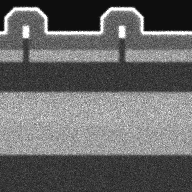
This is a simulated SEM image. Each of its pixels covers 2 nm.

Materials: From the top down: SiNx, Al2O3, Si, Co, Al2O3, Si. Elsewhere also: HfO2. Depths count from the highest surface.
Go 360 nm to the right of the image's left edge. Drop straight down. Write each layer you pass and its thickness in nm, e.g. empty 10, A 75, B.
empty 48, SiNx 36, Al2O3 24, Si 60, Co 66, Al2O3 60, Si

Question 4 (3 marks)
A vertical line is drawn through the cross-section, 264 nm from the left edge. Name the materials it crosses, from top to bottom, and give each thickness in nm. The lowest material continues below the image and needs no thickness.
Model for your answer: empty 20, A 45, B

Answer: SiNx 84, Al2O3 24, Si 60, Co 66, Al2O3 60, Si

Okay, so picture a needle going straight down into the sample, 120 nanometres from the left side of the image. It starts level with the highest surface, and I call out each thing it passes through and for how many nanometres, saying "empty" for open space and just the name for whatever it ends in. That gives empty 48, SiNx 36, Al2O3 24, Si 60, Co 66, Al2O3 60, Si